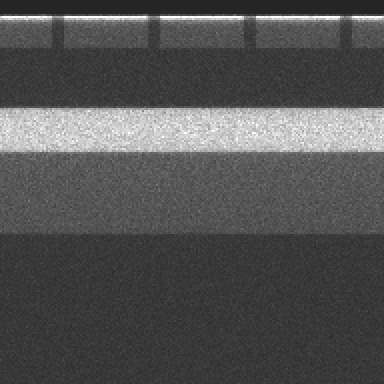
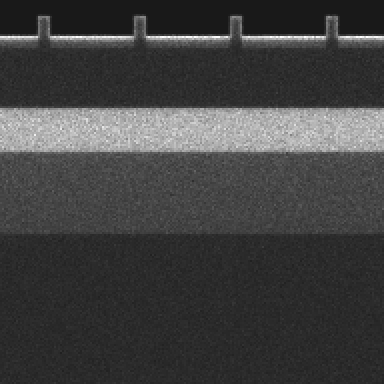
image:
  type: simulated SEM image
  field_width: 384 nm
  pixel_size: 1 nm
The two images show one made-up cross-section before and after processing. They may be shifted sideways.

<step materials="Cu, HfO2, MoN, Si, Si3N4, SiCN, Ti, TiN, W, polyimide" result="removed Si3N4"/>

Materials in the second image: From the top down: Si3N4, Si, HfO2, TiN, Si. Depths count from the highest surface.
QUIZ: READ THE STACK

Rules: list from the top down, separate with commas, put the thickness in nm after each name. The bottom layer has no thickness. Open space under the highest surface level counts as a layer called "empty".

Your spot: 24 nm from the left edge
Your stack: empty 20, Si3N4 12, Si 60, HfO2 44, TiN 82, Si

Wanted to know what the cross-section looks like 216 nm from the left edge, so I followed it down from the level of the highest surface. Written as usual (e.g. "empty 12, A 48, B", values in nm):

empty 20, Si3N4 12, Si 60, HfO2 44, TiN 82, Si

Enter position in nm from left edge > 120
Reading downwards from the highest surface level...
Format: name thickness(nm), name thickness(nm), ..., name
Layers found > empty 20, Si3N4 12, Si 60, HfO2 44, TiN 82, Si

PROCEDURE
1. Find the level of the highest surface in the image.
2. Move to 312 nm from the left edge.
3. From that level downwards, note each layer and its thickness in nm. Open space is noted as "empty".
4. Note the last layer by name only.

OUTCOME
empty 20, Si3N4 12, Si 60, HfO2 44, TiN 82, Si